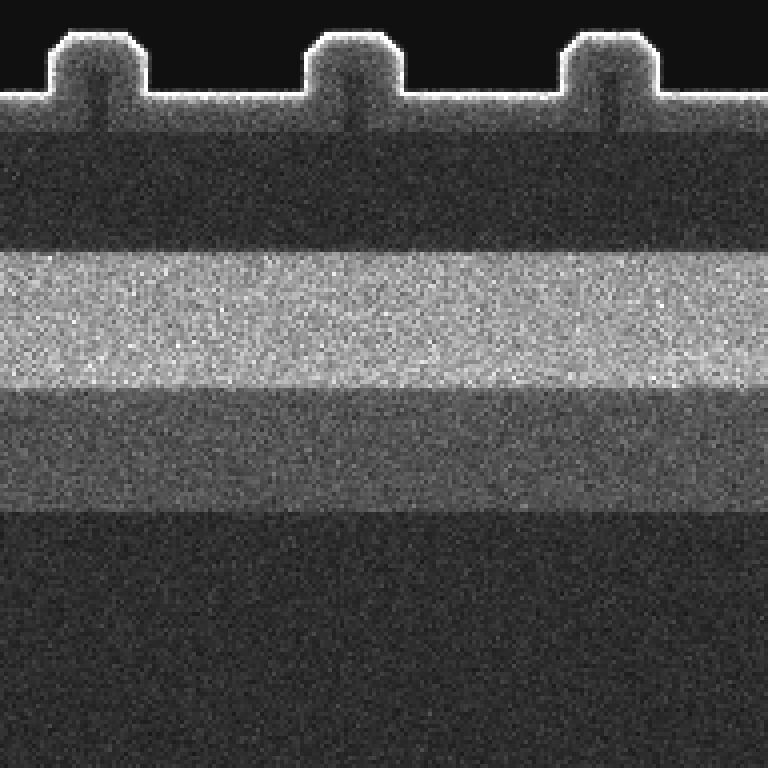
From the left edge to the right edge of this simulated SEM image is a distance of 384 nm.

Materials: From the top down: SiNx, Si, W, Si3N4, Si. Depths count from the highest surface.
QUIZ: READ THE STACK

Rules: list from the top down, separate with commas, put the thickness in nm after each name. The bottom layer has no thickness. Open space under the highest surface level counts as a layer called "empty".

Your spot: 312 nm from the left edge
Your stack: SiNx 50, Si 60, W 68, Si3N4 62, Si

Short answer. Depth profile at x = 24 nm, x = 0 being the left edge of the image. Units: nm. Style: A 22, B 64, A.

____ empty 10, SiNx 40, Si 60, W 68, Si3N4 62, Si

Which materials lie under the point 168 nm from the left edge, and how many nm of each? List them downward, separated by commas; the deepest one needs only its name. SiNx 50, Si 60, W 68, Si3N4 62, Si